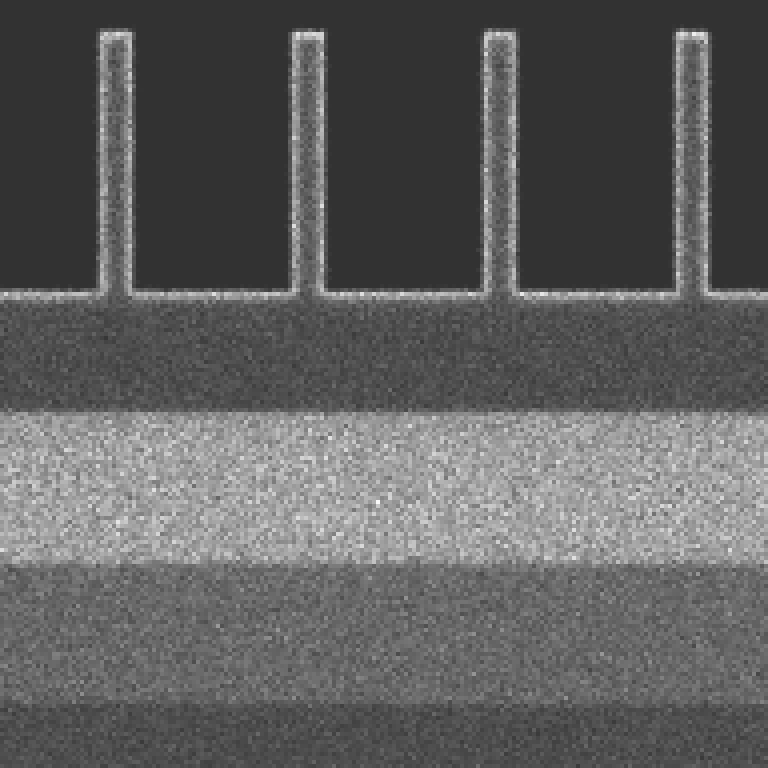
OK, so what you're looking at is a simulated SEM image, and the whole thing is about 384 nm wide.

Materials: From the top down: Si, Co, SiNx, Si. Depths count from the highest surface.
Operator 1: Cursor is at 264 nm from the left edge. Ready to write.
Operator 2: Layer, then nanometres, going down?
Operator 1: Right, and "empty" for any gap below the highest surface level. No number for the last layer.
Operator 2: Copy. empty 130, Si 60, Co 76, SiNx 70, Si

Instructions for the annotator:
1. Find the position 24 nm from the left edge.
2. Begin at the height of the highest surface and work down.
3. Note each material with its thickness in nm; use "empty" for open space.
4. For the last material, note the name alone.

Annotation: empty 130, Si 60, Co 76, SiNx 70, Si